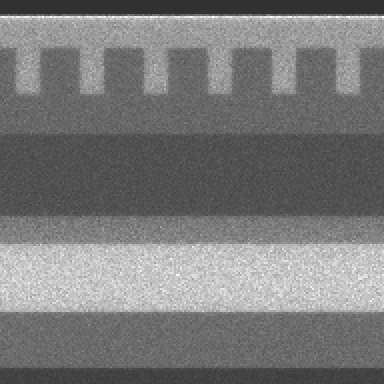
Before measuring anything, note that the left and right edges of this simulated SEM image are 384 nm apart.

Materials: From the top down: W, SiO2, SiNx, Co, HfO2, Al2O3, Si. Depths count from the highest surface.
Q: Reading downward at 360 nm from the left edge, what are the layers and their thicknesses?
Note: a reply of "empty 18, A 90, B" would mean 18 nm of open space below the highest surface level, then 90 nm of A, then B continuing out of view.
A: W 32, SiO2 86, SiNx 82, Co 28, HfO2 68, Al2O3 56, Si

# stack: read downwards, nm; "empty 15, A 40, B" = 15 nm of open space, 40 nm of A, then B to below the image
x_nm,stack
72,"W 32, SiO2 86, SiNx 82, Co 28, HfO2 68, Al2O3 56, Si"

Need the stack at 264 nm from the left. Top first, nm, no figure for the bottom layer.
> W 32, SiO2 86, SiNx 82, Co 28, HfO2 68, Al2O3 56, Si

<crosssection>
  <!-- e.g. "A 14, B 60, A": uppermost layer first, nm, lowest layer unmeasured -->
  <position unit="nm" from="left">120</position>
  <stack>W 32, SiO2 86, SiNx 82, Co 28, HfO2 68, Al2O3 56, Si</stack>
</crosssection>